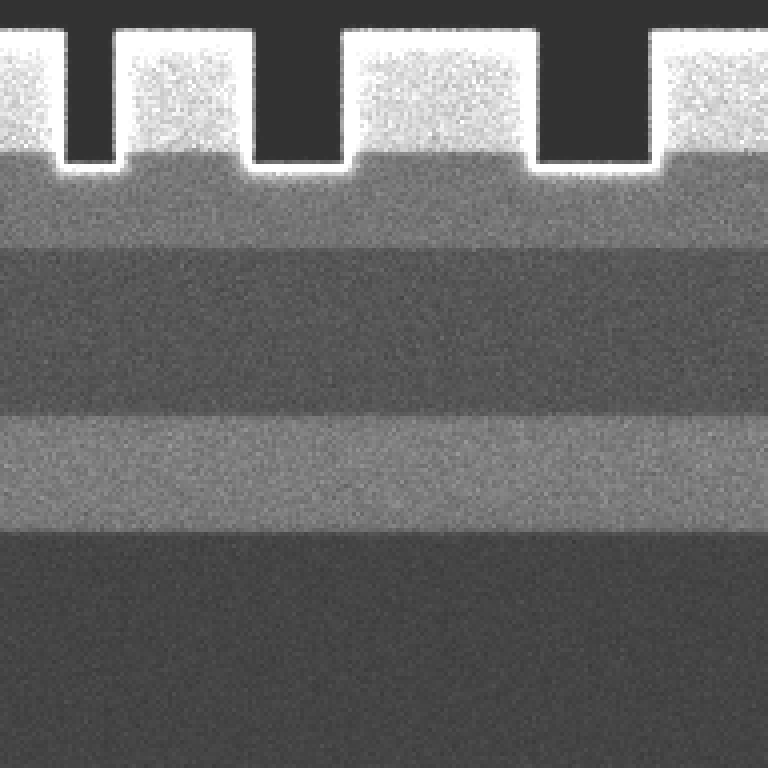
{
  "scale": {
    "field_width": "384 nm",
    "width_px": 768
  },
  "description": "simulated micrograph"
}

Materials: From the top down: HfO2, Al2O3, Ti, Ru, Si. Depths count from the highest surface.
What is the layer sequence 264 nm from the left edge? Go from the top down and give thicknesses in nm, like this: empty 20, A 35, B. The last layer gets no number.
HfO2 60, Al2O3 48, Ti 84, Ru 58, Si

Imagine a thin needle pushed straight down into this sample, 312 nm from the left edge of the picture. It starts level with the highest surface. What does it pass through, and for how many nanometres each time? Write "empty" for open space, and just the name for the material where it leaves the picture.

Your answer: empty 66, Al2O3 42, Ti 84, Ru 58, Si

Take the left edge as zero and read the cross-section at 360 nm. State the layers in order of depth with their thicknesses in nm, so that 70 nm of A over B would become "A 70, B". HfO2 60, Al2O3 48, Ti 84, Ru 58, Si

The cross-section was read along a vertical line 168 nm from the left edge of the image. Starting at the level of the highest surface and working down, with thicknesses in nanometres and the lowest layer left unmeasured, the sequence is empty 66, Al2O3 42, Ti 84, Ru 58, Si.